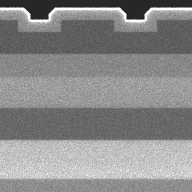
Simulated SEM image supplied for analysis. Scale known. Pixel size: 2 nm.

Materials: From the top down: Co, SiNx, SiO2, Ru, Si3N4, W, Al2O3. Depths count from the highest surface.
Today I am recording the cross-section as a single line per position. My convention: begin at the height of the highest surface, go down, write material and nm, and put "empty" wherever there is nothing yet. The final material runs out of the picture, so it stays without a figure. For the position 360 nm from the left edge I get Co 24, SiNx 68, SiO2 46, Ru 62, Si3N4 64, W 78, Al2O3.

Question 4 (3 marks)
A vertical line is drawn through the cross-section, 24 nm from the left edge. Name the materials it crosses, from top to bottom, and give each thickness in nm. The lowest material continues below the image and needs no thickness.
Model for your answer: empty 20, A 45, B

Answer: Co 24, SiNx 68, SiO2 46, Ru 62, Si3N4 64, W 78, Al2O3